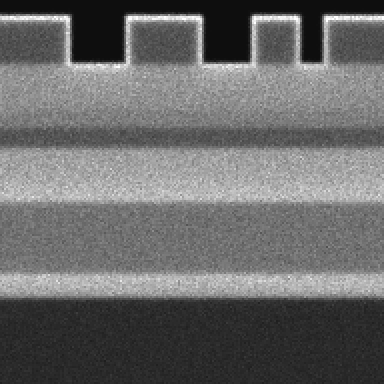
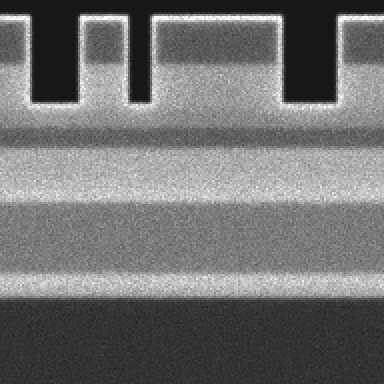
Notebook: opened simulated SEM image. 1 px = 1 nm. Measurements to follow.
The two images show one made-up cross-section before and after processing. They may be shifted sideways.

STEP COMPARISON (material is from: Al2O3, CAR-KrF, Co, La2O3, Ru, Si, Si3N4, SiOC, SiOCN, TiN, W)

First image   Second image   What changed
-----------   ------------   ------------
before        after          Ru, removed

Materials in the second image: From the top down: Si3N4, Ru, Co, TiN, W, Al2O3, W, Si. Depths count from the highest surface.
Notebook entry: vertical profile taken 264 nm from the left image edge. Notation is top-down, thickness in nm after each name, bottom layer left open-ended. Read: Si3N4 48, Ru 46, Co 18, TiN 20, W 54, Al2O3 72, W 24, Si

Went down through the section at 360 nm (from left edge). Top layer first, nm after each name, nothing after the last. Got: Si3N4 48, Ru 46, Co 18, TiN 20, W 54, Al2O3 72, W 24, Si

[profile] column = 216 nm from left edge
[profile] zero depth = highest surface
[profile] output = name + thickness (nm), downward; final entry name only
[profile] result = Si3N4 48, Ru 46, Co 18, TiN 20, W 54, Al2O3 72, W 24, Si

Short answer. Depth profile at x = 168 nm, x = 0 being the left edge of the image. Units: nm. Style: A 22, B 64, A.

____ Si3N4 48, Ru 46, Co 18, TiN 20, W 54, Al2O3 72, W 24, Si